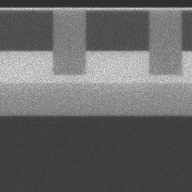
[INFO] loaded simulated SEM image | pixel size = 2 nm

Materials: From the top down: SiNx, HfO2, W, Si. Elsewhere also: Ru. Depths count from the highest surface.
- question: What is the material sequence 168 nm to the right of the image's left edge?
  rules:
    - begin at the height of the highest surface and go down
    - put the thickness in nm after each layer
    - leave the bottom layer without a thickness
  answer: Ru 134, HfO2 16, W 66, Si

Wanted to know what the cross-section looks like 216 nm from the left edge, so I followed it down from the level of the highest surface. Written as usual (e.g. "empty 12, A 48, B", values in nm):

SiNx 86, HfO2 64, W 66, Si